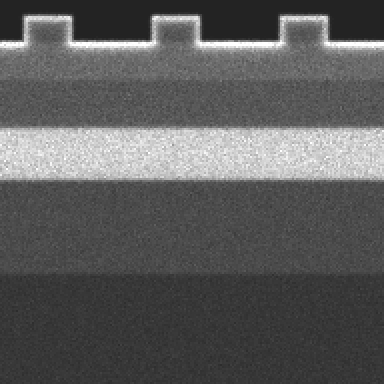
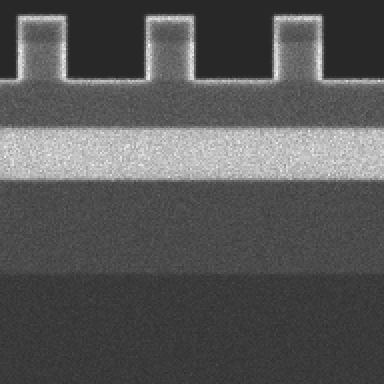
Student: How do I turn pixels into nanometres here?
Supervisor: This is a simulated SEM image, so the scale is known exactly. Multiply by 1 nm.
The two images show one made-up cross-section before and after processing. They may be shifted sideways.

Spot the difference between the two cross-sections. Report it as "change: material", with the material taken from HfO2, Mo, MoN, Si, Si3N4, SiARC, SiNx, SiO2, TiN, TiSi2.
removed: SiO2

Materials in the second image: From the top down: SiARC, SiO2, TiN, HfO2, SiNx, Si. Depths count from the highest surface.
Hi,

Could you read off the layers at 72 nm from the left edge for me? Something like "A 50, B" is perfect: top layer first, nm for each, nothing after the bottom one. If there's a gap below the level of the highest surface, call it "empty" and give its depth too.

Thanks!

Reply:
empty 64, TiN 48, HfO2 52, SiNx 94, Si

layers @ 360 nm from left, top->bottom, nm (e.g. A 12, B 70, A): empty 64, TiN 48, HfO2 52, SiNx 94, Si